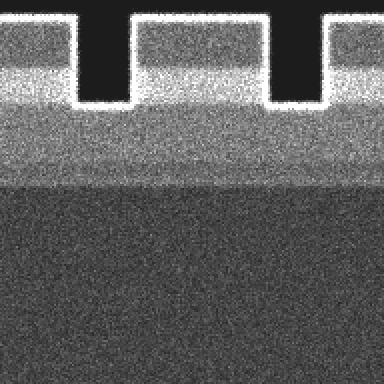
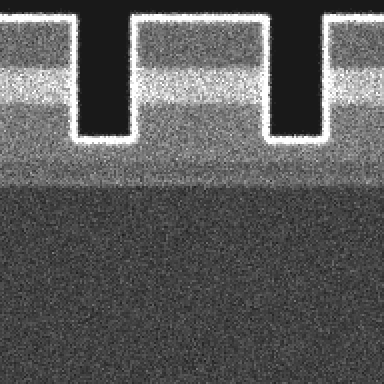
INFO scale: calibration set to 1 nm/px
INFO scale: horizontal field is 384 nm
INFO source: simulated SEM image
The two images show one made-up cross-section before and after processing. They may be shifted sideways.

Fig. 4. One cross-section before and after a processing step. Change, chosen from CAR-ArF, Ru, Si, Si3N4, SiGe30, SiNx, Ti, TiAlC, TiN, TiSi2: Si3N4 removed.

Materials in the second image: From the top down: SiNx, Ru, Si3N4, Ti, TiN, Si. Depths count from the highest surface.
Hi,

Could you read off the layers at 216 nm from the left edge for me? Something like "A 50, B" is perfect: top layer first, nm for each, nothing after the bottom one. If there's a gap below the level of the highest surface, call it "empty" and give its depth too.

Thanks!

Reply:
SiNx 52, Ru 36, Si3N4 58, Ti 16, TiN 8, Si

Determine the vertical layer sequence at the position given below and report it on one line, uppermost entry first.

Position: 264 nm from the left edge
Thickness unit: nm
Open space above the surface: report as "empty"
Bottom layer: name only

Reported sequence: SiNx 52, Ru 36, Si3N4 58, Ti 16, TiN 8, Si